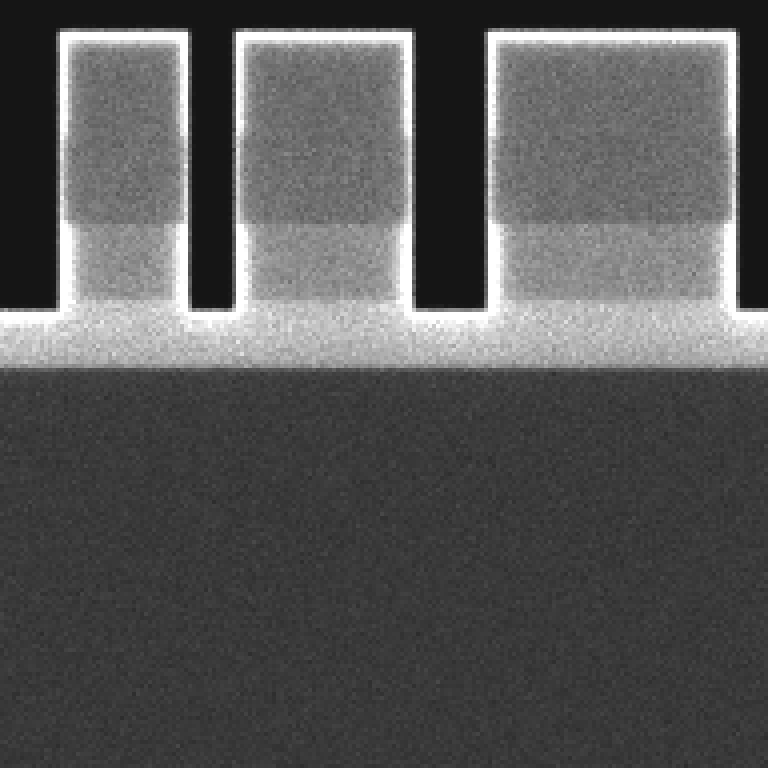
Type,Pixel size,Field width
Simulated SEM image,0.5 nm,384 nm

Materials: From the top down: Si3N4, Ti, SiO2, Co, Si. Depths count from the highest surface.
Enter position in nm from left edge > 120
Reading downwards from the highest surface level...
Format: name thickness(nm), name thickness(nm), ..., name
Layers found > Si3N4 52, Ti 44, SiO2 38, Co 34, Si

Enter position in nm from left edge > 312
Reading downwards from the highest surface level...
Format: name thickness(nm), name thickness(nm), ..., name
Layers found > Si3N4 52, Ti 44, SiO2 38, Co 34, Si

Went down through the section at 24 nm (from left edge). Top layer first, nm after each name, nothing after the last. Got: empty 140, Co 28, Si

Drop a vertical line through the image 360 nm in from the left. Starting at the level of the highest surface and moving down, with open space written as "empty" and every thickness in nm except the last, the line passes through Si3N4 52, Ti 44, SiO2 38, Co 34, Si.